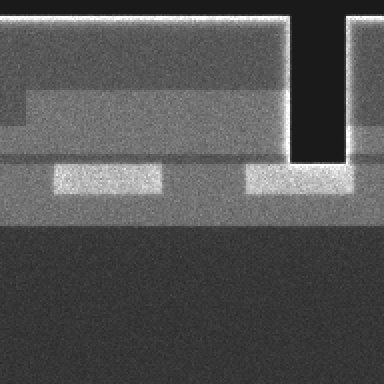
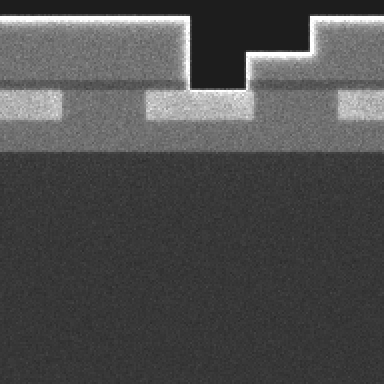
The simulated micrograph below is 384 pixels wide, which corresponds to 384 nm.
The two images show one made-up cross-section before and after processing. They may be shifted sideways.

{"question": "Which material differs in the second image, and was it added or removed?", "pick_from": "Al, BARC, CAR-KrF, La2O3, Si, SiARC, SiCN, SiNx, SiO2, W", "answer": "SiARC, removed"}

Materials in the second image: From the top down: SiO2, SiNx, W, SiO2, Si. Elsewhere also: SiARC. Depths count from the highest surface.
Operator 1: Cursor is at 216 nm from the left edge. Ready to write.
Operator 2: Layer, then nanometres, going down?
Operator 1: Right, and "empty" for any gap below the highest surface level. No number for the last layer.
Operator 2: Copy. empty 74, W 30, SiO2 32, Si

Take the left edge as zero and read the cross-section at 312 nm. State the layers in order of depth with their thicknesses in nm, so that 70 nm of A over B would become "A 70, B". SiO2 64, SiNx 10, SiO2 62, Si